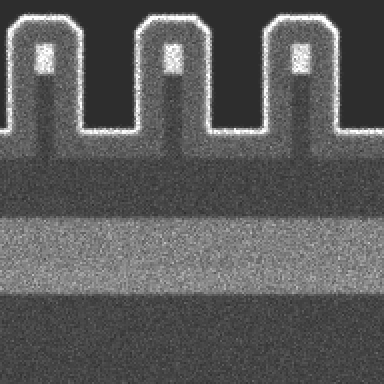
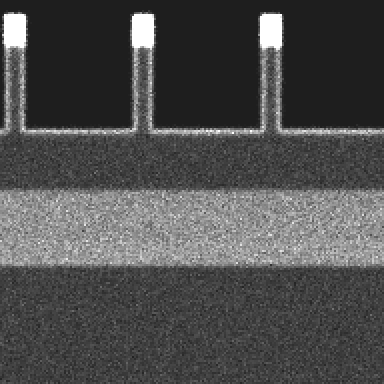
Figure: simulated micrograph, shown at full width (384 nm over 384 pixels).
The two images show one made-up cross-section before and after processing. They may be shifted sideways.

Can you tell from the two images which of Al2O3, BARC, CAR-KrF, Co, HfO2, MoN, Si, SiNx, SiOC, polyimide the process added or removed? Yes, it removed SiNx.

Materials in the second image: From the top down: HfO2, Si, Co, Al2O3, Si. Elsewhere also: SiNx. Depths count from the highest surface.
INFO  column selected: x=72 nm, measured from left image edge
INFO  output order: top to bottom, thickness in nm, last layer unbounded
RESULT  empty 114, Si 60, Co 52, Al2O3 24, Si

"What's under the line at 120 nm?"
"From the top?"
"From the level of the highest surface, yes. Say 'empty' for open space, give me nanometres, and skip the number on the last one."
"empty 114, Si 60, Co 52, Al2O3 24, Si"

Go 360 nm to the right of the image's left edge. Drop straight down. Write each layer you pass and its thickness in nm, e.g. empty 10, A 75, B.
empty 114, Si 60, Co 52, Al2O3 24, Si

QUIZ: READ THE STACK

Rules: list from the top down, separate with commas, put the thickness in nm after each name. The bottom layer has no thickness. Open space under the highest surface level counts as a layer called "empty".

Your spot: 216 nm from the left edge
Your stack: empty 114, Si 60, Co 52, Al2O3 24, Si